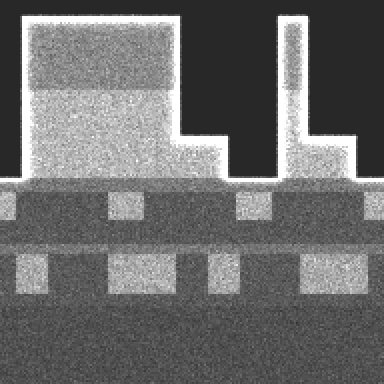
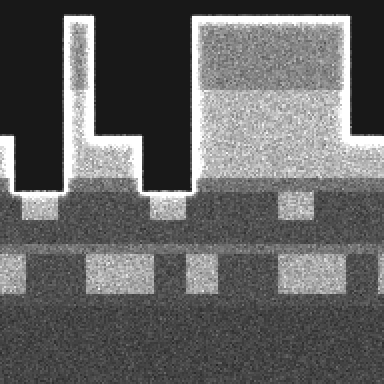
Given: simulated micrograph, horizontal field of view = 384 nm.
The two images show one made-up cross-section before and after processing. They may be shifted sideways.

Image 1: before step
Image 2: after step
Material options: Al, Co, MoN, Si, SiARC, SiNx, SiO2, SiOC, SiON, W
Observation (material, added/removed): SiNx, removed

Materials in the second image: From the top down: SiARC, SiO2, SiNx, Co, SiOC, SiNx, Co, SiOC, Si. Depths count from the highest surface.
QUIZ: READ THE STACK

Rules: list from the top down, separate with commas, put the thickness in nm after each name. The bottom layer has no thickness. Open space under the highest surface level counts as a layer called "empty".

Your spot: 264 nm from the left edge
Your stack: SiARC 74, SiO2 88, SiNx 14, SiOC 52, SiNx 10, SiOC 52, Si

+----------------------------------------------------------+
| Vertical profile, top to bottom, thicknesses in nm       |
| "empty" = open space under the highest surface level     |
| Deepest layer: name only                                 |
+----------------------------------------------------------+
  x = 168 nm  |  empty 176, Co 28, SiOC 24, SiNx 10, SiOC 52, Si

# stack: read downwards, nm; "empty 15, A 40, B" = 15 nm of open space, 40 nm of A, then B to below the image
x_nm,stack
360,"empty 120, SiO2 42, SiNx 14, SiOC 52, SiNx 10, SiOC 52, Si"